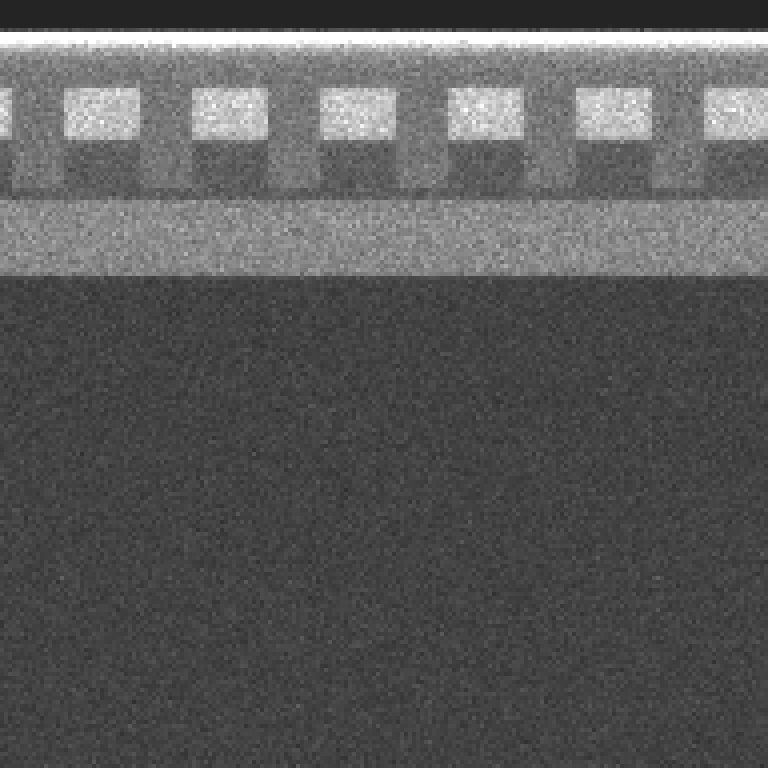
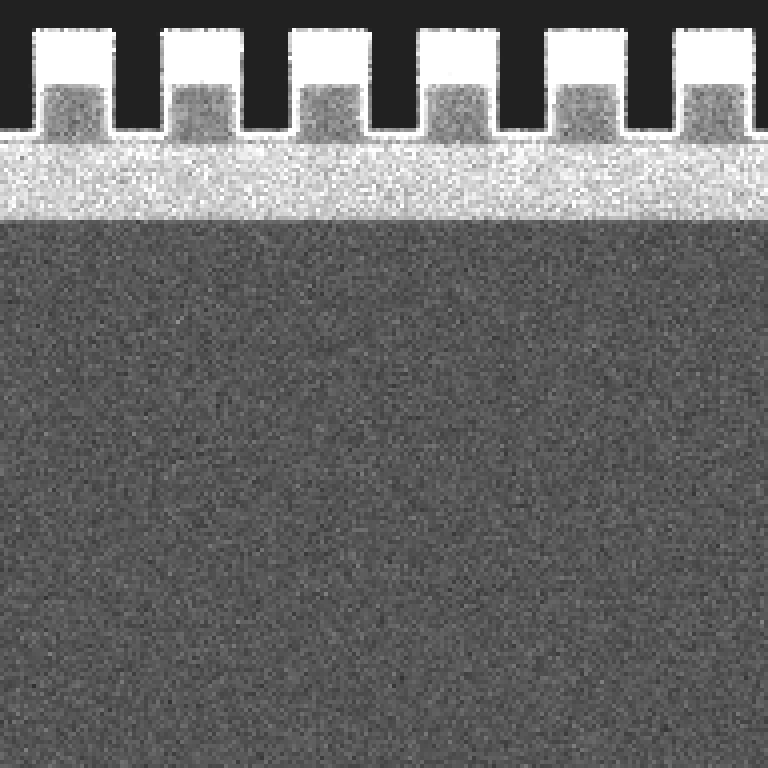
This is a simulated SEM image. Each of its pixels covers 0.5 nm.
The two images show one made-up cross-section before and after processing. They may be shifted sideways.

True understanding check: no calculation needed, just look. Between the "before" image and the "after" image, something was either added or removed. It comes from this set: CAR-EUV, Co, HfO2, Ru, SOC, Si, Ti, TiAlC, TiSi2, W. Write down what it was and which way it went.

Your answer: SOC (removed)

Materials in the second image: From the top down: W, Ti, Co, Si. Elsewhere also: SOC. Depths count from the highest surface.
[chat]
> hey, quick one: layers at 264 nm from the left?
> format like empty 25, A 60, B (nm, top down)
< empty 50, Ti 6, Co 38, Si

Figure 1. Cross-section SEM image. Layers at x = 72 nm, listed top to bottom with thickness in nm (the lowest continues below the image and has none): empty 50, Ti 6, Co 38, Si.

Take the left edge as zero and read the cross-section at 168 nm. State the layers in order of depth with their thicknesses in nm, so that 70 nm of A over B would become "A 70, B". W 26, Ti 30, Co 38, Si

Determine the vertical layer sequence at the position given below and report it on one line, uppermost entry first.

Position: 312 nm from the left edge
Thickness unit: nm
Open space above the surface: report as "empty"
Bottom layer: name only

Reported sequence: empty 50, Ti 6, Co 38, Si